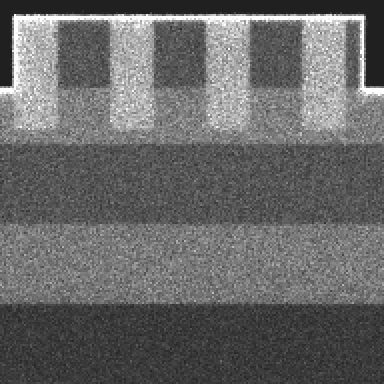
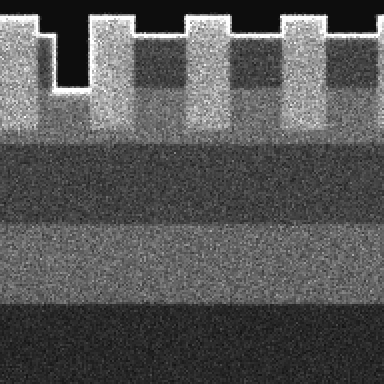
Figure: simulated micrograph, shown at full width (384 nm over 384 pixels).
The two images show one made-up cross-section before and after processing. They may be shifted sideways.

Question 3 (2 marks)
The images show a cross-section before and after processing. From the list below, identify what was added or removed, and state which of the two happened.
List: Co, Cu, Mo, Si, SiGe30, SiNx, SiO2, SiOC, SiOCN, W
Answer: SiNx was removed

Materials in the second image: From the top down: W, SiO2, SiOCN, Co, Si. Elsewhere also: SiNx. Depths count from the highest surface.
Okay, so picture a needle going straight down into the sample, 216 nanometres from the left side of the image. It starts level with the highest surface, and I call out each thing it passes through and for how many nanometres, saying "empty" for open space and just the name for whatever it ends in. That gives W 114, SiO2 14, SiOCN 80, Co 80, Si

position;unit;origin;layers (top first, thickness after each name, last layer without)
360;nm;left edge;empty 18, SiNx 54, SiO2 56, SiOCN 80, Co 80, Si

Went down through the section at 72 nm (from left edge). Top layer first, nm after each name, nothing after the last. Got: empty 72, SiO2 56, SiOCN 80, Co 80, Si